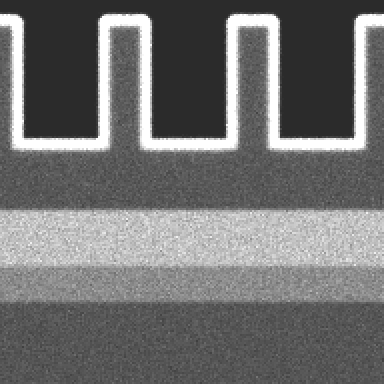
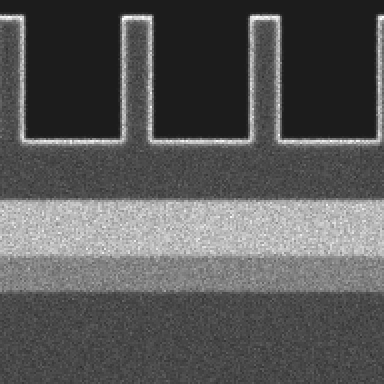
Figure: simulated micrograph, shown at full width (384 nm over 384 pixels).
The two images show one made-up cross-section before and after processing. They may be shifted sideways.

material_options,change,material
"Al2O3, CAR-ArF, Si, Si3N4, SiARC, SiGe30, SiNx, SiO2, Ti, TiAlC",removed,SiO2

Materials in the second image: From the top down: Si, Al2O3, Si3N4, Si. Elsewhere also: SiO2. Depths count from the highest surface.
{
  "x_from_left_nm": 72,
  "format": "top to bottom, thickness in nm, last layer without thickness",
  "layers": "empty 124, Si 60, Al2O3 56, Si3N4 36, Si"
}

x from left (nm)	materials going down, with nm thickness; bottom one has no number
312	empty 124, Si 60, Al2O3 56, Si3N4 36, Si